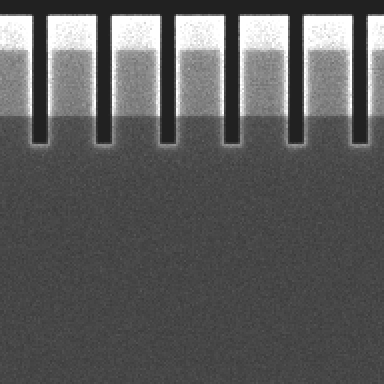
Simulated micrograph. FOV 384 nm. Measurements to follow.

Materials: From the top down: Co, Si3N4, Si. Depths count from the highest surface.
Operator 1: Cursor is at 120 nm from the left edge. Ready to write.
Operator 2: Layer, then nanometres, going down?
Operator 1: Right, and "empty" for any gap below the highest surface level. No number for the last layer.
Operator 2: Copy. Co 34, Si3N4 66, Si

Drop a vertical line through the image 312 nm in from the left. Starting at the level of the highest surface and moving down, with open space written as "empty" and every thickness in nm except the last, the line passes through Co 34, Si3N4 66, Si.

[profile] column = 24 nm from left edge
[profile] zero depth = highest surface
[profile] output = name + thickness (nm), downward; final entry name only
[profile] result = Co 34, Si3N4 66, Si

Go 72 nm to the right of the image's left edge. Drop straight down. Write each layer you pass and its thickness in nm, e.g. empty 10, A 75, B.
Co 34, Si3N4 66, Si